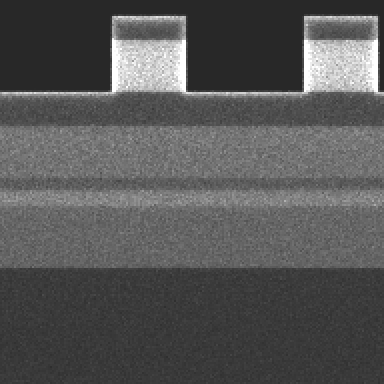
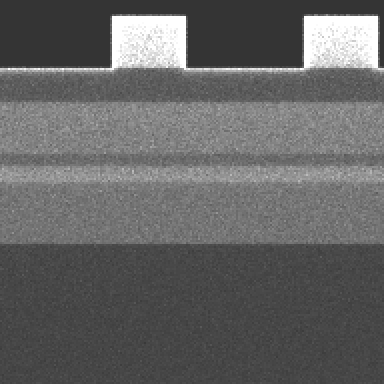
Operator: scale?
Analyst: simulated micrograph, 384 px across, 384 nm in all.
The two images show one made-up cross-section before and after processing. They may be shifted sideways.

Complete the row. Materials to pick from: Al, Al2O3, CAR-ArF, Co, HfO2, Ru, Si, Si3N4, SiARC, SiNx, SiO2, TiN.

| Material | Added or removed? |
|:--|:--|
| SiARC | removed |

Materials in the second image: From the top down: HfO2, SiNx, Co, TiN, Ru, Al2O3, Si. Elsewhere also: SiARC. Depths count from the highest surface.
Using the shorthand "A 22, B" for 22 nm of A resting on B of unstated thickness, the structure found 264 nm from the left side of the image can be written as empty 52, SiNx 34, Co 52, TiN 12, Ru 16, Al2O3 62, Si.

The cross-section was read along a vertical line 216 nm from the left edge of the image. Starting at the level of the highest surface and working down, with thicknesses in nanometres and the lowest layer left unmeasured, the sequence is empty 52, SiNx 34, Co 52, TiN 12, Ru 16, Al2O3 62, Si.